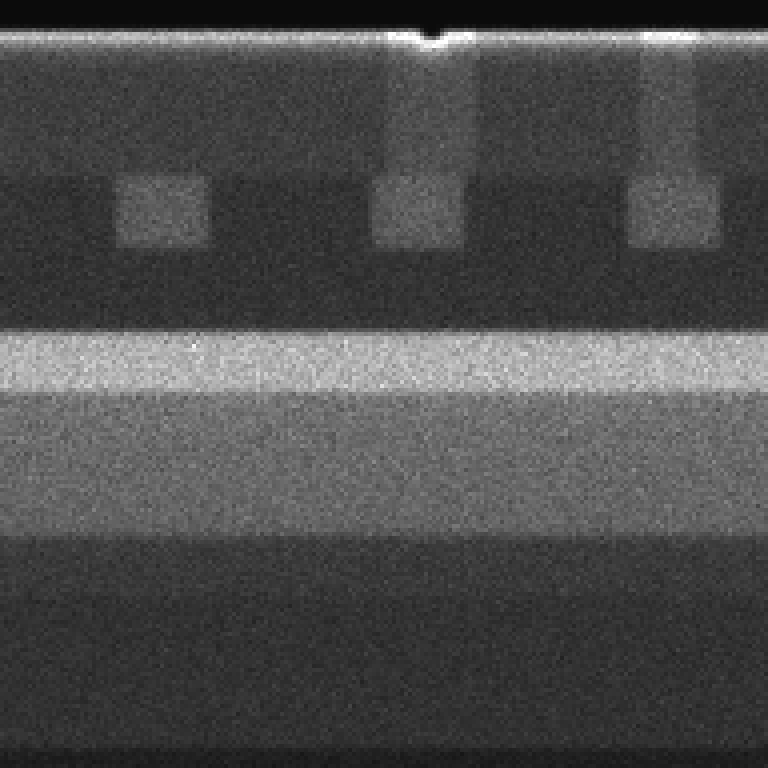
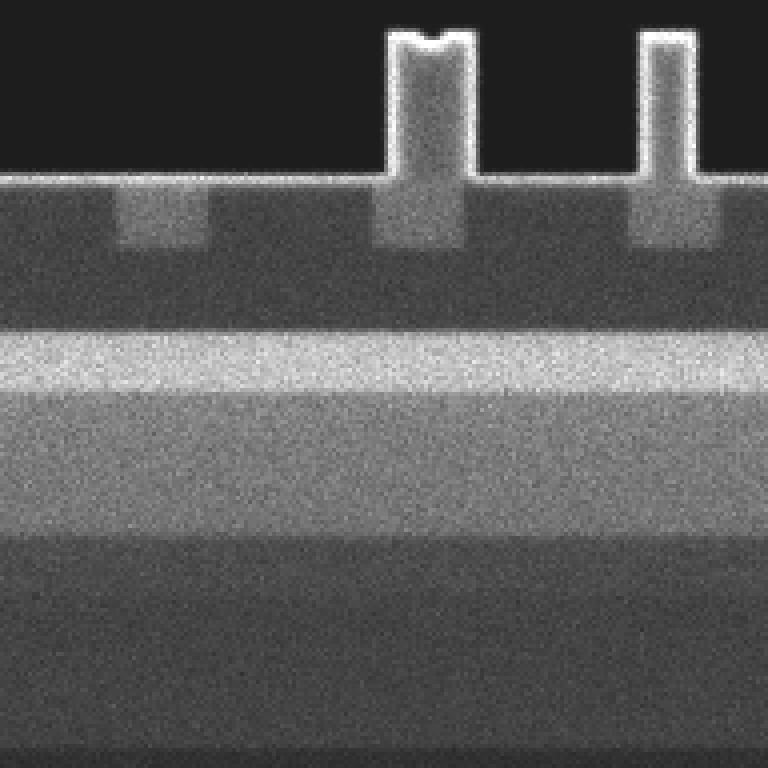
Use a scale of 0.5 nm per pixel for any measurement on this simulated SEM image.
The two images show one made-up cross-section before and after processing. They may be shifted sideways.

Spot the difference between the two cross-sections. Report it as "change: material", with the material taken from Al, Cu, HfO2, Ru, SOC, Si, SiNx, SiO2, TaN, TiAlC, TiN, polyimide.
removed: SOC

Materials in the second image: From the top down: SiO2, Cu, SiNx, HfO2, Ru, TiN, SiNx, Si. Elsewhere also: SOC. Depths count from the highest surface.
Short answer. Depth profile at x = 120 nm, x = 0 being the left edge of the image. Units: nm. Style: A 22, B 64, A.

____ empty 72, SiNx 78, HfO2 30, Ru 72, TiN 30, SiNx 76, Si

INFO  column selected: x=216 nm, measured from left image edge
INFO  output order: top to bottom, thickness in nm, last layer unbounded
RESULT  empty 4, SiO2 68, Cu 36, SiNx 42, HfO2 30, Ru 72, TiN 30, SiNx 76, Si